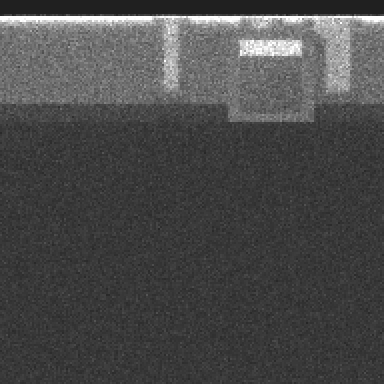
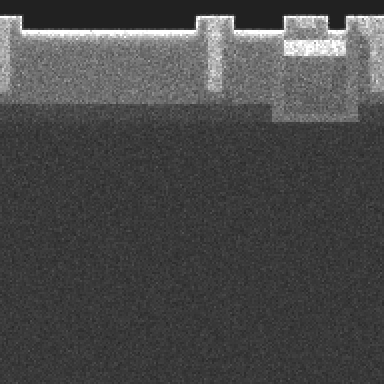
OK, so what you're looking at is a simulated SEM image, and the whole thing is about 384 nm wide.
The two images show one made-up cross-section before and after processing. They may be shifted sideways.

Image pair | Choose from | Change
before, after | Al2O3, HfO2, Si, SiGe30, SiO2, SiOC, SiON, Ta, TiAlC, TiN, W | SiO2 (removed)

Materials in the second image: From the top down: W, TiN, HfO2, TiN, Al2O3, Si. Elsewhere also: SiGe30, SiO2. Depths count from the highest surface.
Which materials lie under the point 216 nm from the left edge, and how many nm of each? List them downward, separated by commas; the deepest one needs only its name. W 76, TiN 12, SiGe30 18, Si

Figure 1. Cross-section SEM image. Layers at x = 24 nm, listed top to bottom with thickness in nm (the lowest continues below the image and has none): empty 14, SiO2 74, SiGe30 18, Si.